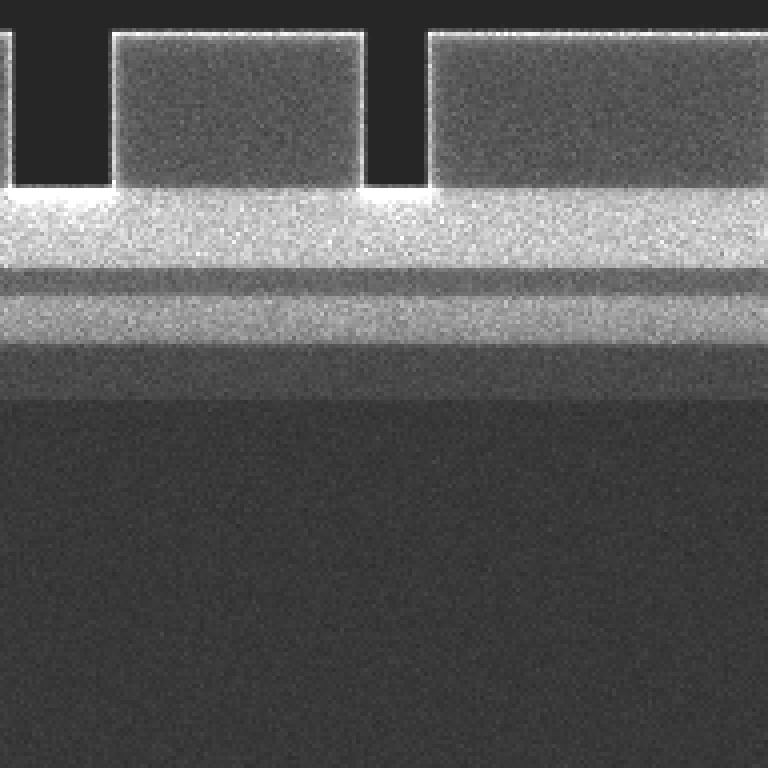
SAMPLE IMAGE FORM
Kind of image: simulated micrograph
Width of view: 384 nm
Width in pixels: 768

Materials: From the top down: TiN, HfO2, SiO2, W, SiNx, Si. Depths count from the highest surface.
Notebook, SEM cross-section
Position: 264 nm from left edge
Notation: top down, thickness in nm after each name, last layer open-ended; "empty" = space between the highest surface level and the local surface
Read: TiN 78, HfO2 40, SiO2 14, W 24, SiNx 28, Si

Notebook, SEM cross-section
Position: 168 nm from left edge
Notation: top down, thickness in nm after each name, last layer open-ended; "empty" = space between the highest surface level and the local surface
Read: TiN 78, HfO2 40, SiO2 14, W 24, SiNx 28, Si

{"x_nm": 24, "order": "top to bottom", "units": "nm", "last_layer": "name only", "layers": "empty 78, HfO2 40, SiO2 14, W 24, SiNx 28, Si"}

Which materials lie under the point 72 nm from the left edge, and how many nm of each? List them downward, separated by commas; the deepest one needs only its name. TiN 78, HfO2 40, SiO2 14, W 24, SiNx 28, Si